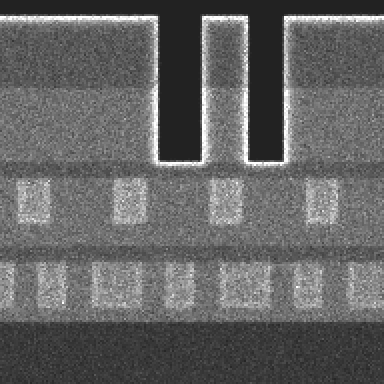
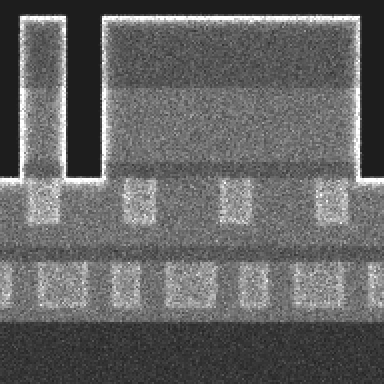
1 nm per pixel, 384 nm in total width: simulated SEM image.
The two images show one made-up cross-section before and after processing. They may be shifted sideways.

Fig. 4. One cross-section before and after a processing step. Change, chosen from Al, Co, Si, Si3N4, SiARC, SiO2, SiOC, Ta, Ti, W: Si3N4 removed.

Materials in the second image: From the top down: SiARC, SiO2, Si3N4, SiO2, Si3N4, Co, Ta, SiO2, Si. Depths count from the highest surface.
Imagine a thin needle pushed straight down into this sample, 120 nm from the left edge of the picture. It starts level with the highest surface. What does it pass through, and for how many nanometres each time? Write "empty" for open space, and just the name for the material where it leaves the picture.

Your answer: SiARC 72, SiO2 74, Si3N4 16, SiO2 68, Si3N4 16, Co 40, Ta 6, SiO2 14, Si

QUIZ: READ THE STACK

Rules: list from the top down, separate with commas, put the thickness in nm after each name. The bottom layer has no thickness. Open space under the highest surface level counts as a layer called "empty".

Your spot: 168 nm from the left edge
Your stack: SiARC 72, SiO2 74, Si3N4 16, SiO2 68, Si3N4 16, Ta 46, SiO2 14, Si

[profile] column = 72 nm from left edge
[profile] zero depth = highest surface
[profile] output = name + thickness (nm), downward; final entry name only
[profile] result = empty 162, SiO2 68, Si3N4 16, Co 40, Ta 6, SiO2 14, Si